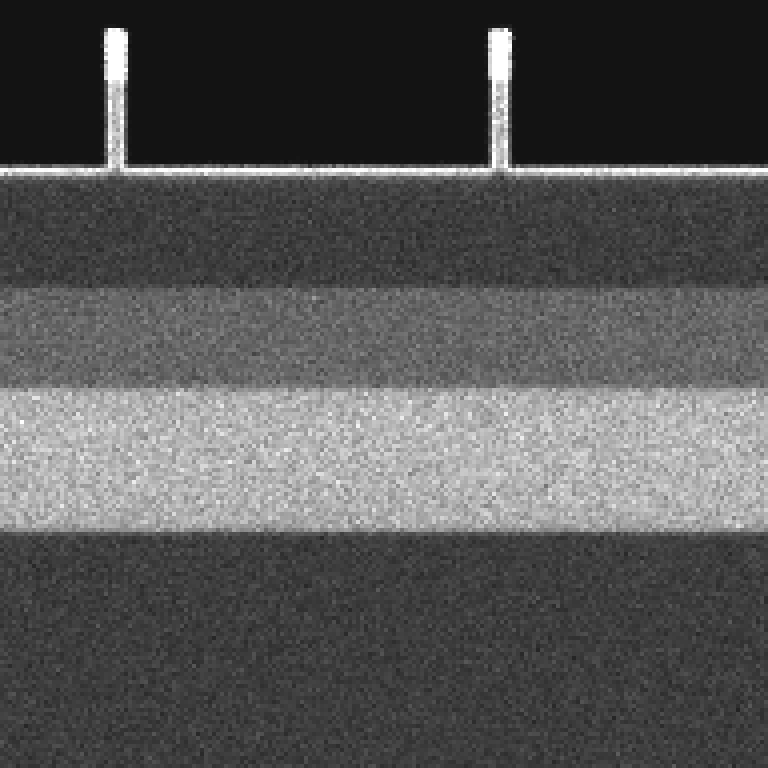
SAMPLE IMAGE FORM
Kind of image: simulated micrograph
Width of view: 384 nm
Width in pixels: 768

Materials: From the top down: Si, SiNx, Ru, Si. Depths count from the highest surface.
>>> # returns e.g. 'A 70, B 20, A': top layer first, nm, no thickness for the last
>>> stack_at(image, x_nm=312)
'empty 68, Si 60, SiNx 50, Ru 72, Si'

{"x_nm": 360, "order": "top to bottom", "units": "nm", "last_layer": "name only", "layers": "empty 68, Si 60, SiNx 50, Ru 72, Si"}